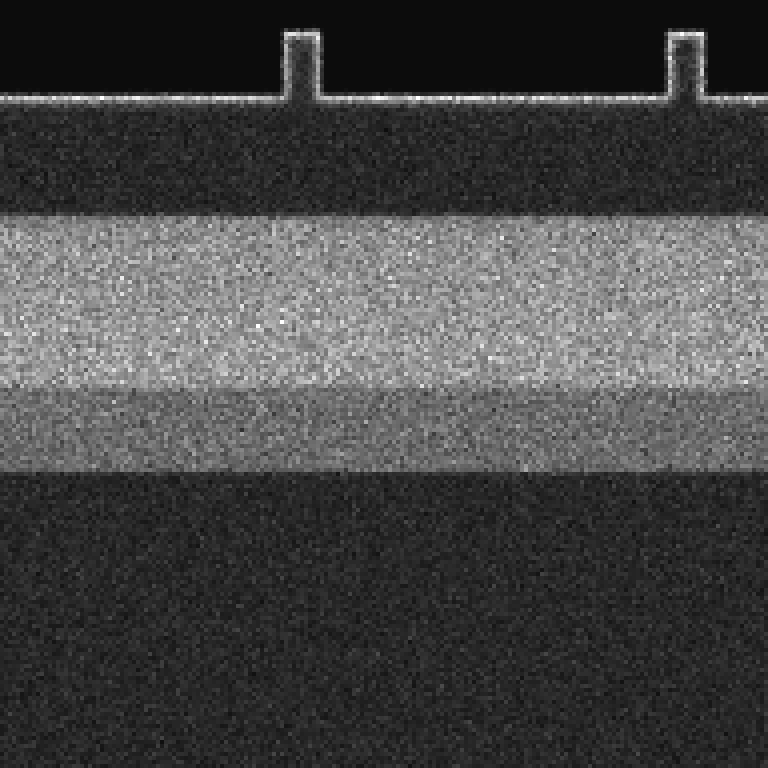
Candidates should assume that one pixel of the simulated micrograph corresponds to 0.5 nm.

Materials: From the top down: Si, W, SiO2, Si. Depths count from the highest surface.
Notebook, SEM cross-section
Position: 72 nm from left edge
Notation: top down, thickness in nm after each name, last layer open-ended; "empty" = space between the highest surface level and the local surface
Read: empty 32, Si 60, W 86, SiO2 42, Si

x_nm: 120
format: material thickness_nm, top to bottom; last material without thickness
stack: empty 32, Si 60, W 86, SiO2 42, Si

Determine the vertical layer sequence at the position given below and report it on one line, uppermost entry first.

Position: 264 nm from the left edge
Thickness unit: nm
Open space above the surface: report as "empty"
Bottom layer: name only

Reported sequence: empty 32, Si 60, W 86, SiO2 42, Si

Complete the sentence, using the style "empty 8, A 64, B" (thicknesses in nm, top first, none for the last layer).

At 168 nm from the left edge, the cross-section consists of empty 32, Si 60, W 86, SiO2 42, Si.